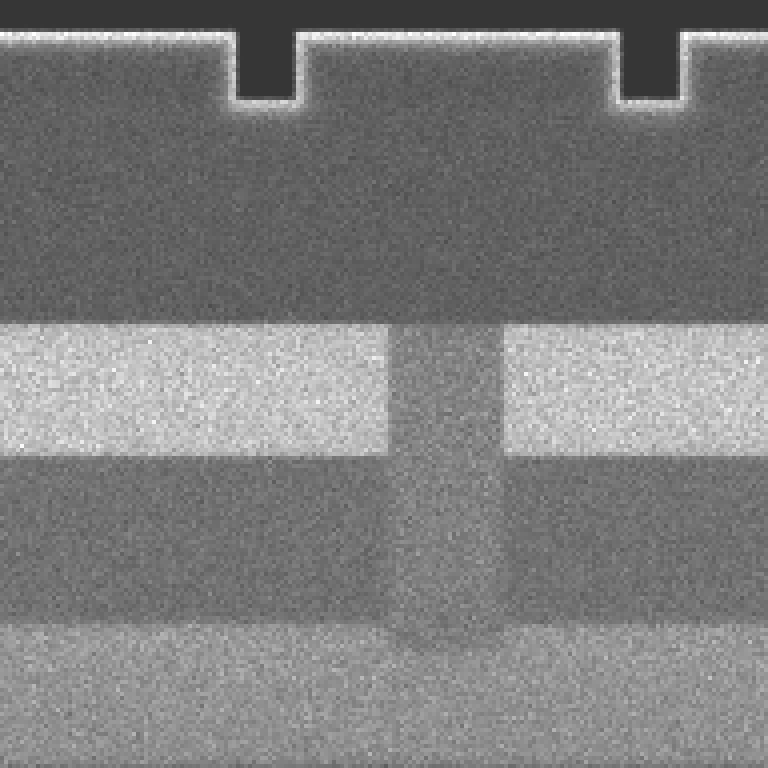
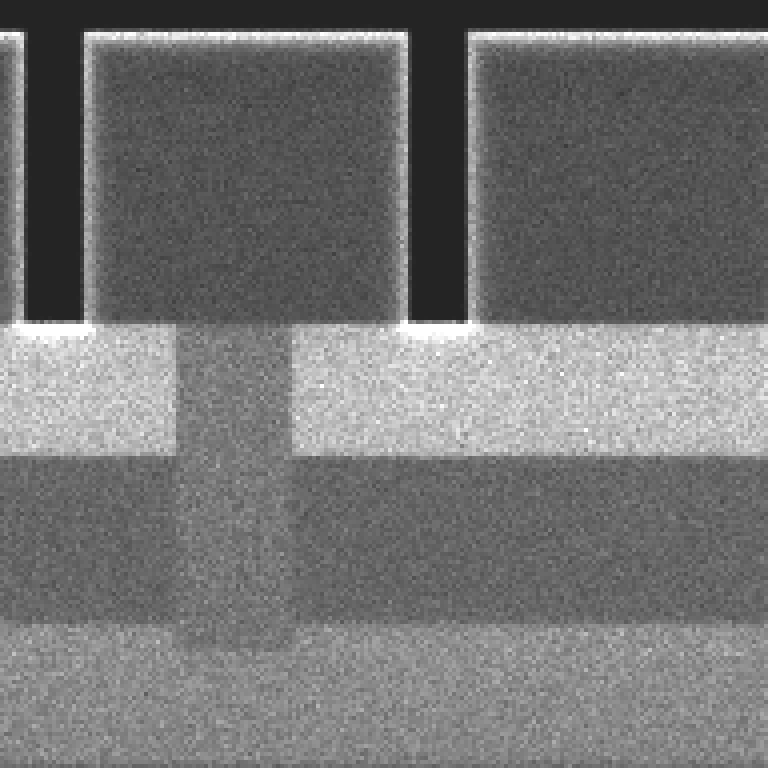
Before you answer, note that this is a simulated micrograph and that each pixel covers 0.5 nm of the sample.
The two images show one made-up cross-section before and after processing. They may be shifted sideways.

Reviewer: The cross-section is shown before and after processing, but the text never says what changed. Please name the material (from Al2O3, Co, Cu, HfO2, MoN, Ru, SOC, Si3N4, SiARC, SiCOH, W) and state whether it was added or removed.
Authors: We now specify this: SOC, removed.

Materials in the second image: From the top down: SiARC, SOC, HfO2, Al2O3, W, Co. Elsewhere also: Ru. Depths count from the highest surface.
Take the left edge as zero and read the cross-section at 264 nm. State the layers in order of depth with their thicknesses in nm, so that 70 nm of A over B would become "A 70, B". SiARC 34, SOC 112, HfO2 66, Al2O3 84, W 70, Co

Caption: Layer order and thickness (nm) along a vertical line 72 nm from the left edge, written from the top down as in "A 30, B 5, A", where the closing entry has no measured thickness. SiARC 34, SOC 112, HfO2 66, Al2O3 84, W 70, Co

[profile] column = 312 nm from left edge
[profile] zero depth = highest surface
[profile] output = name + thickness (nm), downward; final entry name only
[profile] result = SiARC 34, SOC 112, HfO2 66, Al2O3 84, W 70, Co